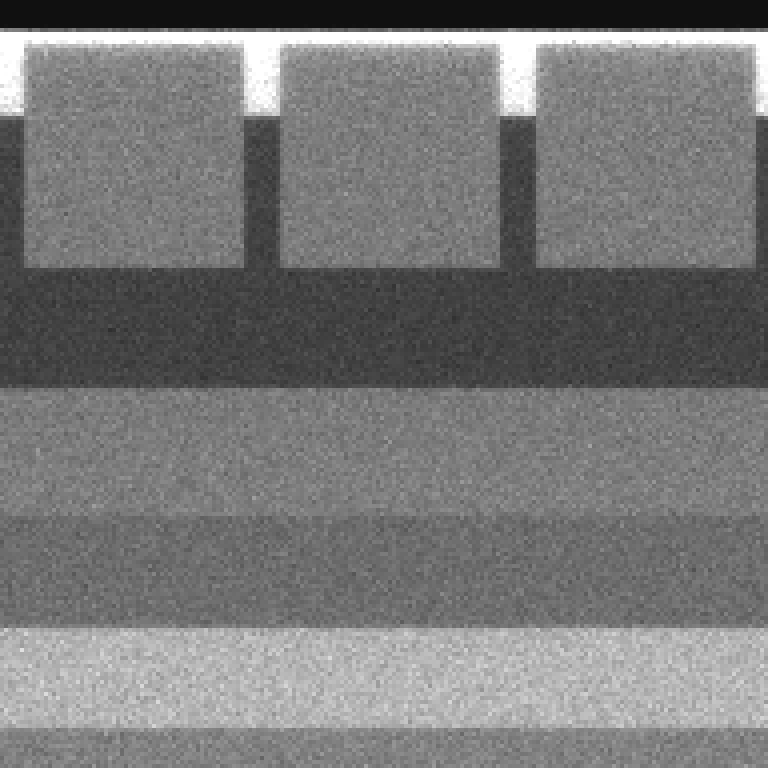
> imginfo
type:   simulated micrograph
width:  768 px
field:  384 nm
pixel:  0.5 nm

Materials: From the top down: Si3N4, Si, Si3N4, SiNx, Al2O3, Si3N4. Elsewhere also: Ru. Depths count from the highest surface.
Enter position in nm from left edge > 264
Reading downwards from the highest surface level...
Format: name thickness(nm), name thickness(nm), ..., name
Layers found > Ru 42, Si 136, Si3N4 64, SiNx 56, Al2O3 50, Si3N4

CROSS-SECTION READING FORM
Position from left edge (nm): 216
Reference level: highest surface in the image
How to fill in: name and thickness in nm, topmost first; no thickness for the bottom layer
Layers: Si3N4 118, Si 60, Si3N4 64, SiNx 56, Al2O3 50, Si3N4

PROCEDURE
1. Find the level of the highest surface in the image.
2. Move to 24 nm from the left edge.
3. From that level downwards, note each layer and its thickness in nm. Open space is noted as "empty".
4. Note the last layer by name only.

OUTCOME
Si3N4 118, Si 60, Si3N4 64, SiNx 56, Al2O3 50, Si3N4